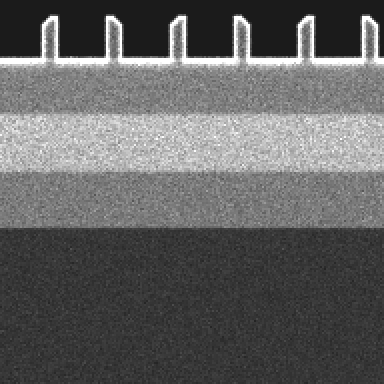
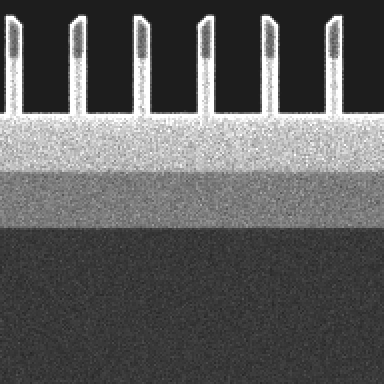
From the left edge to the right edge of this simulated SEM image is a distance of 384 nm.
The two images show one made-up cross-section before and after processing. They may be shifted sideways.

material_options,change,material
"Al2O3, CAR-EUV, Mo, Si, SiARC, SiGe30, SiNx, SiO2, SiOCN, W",removed,Al2O3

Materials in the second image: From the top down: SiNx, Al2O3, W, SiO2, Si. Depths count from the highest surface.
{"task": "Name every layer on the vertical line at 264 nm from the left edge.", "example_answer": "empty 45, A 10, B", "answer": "SiNx 42, Al2O3 56, W 58, SiO2 56, Si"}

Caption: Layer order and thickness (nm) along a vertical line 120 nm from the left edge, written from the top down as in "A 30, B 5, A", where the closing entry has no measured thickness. empty 98, W 58, SiO2 56, Si